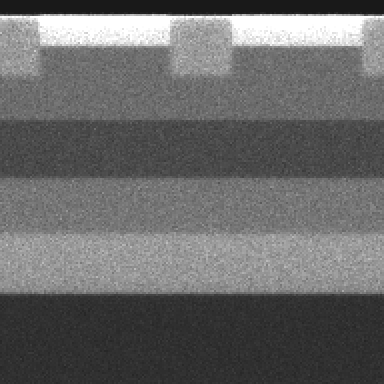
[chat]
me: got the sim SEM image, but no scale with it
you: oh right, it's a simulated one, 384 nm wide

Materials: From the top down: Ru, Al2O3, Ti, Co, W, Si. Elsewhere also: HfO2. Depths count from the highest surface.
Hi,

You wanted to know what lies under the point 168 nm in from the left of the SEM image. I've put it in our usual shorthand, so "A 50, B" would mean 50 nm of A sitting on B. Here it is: HfO2 30, Al2O3 74, Ti 58, Co 56, W 60, Si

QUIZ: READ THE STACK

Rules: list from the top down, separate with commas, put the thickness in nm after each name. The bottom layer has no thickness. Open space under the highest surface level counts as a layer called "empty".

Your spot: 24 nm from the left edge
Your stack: Ru 60, Al2O3 44, Ti 58, Co 56, W 60, Si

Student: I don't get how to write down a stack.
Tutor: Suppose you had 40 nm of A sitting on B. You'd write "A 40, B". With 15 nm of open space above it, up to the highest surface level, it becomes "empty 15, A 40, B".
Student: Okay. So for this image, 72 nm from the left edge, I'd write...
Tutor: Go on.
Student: HfO2 30, Al2O3 74, Ti 58, Co 56, W 60, Si